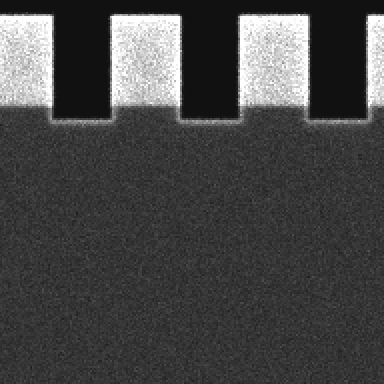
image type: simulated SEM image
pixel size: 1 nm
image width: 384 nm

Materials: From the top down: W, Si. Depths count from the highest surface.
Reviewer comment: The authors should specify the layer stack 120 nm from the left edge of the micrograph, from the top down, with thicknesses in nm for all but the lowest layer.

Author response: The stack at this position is W 90, Si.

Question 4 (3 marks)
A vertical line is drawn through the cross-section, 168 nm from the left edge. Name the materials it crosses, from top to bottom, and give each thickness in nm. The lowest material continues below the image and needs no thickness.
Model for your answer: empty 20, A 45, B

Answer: W 90, Si